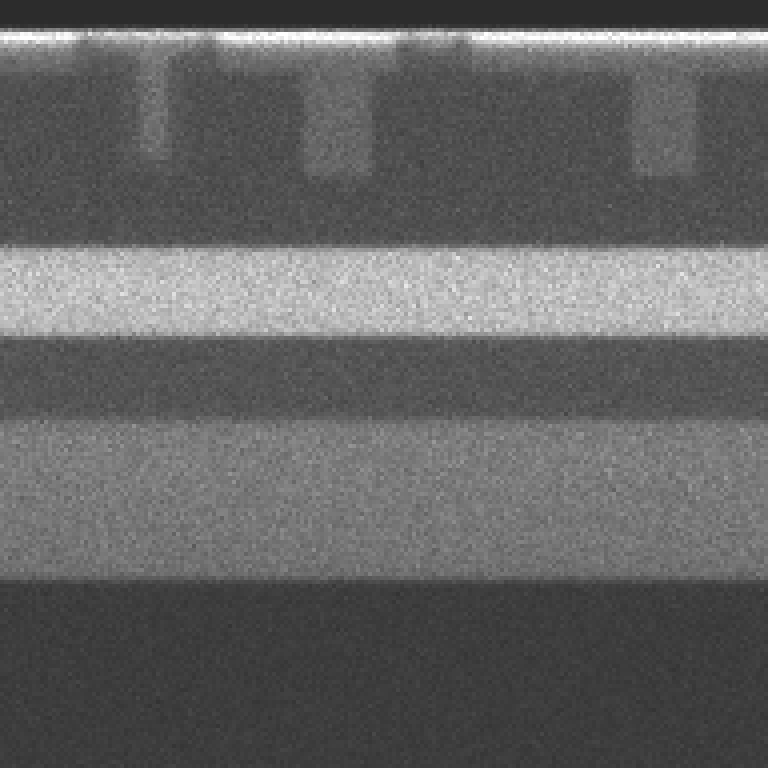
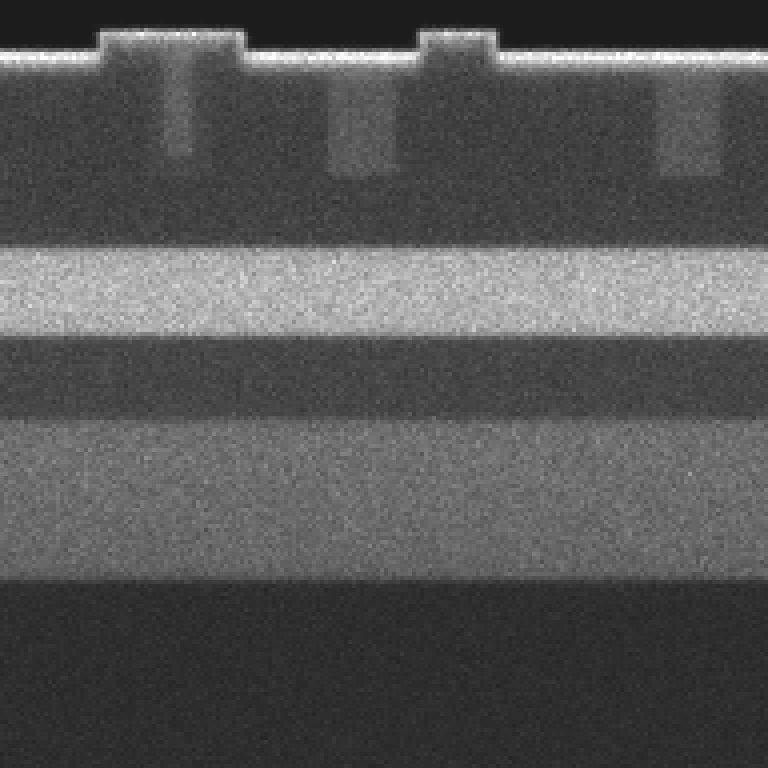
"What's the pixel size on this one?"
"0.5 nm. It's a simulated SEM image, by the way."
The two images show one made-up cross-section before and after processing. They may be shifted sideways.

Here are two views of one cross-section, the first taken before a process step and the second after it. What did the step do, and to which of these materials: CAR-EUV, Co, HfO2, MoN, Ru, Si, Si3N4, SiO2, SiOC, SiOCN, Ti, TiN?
It removed SiO2.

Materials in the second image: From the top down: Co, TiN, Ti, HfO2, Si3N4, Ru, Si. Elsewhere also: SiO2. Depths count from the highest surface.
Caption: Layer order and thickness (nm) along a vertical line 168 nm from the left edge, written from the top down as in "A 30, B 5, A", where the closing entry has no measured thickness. empty 10, SiO2 62, Ti 36, HfO2 44, Si3N4 42, Ru 80, Si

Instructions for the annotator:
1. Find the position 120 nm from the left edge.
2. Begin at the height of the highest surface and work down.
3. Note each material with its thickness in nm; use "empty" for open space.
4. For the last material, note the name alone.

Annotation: TiN 20, Ti 88, HfO2 44, Si3N4 42, Ru 80, Si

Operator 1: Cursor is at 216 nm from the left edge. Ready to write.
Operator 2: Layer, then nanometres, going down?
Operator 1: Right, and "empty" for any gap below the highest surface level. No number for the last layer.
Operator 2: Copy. TiN 20, Ti 88, HfO2 44, Si3N4 42, Ru 80, Si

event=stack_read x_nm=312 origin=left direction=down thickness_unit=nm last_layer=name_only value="empty 10, SiO2 10, Ti 88, HfO2 44, Si3N4 42, Ru 80, Si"